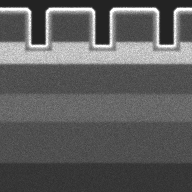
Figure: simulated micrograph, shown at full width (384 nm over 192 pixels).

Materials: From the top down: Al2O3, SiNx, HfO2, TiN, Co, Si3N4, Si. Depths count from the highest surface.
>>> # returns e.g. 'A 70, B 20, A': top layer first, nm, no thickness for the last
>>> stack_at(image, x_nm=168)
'Al2O3 12, SiNx 56, HfO2 44, TiN 60, Co 56, Si3N4 82, Si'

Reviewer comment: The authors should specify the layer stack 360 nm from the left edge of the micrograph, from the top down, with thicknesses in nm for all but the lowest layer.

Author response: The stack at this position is Al2O3 12, SiNx 56, HfO2 44, TiN 60, Co 56, Si3N4 82, Si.